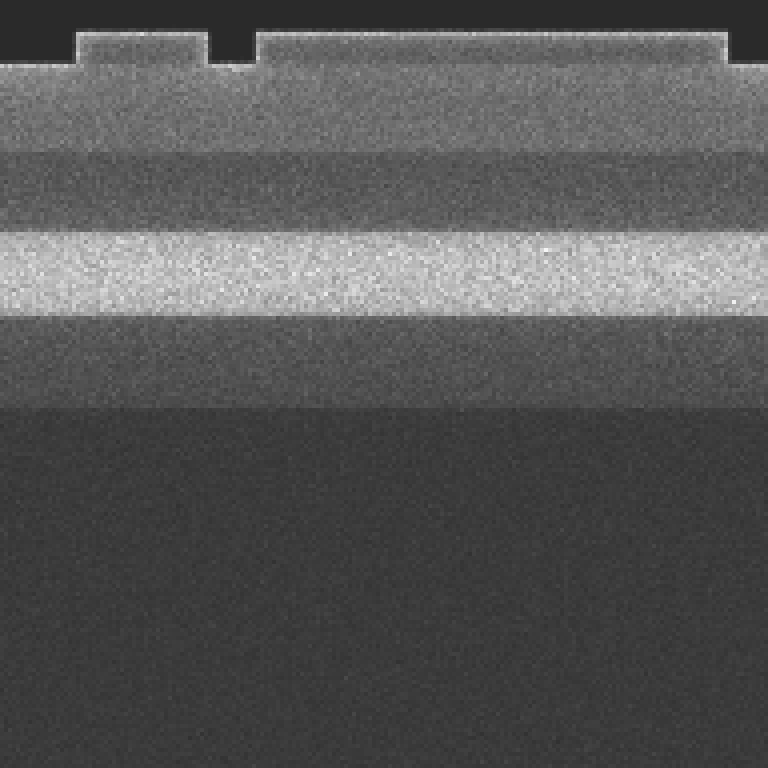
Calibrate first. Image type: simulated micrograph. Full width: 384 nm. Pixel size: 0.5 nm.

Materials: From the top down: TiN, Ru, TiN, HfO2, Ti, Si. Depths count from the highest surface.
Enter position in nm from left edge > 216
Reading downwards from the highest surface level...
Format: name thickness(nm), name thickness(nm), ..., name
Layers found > TiN 16, Ru 44, TiN 40, HfO2 42, Ti 46, Si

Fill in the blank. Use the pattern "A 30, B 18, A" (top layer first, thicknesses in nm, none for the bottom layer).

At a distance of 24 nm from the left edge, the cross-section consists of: empty 16, Ru 44, TiN 40, HfO2 42, Ti 46, Si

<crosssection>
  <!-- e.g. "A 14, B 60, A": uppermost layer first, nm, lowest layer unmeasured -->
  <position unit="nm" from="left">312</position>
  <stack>TiN 16, Ru 44, TiN 40, HfO2 42, Ti 46, Si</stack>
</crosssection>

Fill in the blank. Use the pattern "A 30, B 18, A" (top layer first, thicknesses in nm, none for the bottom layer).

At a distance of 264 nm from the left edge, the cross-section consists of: TiN 16, Ru 44, TiN 40, HfO2 42, Ti 46, Si